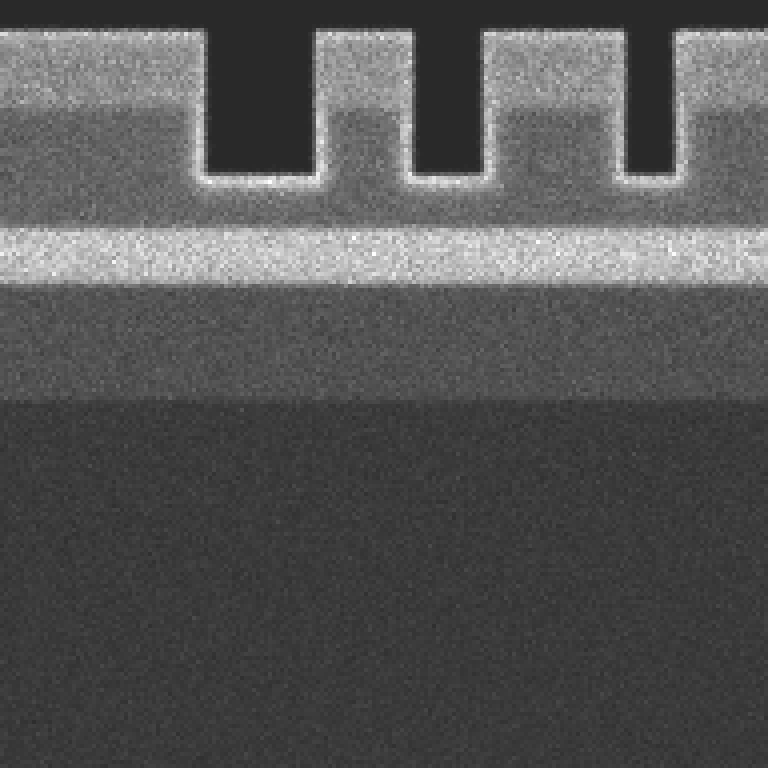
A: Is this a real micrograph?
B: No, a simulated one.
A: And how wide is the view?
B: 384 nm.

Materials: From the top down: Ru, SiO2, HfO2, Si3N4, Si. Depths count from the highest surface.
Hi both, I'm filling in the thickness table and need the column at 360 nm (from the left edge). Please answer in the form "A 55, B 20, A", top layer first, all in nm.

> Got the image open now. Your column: Ru 38, SiO2 60, HfO2 28, Si3N4 58, Si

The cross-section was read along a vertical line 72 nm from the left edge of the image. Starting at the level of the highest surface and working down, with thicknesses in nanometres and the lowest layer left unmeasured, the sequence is Ru 38, SiO2 60, HfO2 28, Si3N4 58, Si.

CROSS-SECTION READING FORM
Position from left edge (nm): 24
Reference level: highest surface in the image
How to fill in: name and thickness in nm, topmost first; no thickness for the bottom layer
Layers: Ru 38, SiO2 60, HfO2 28, Si3N4 58, Si